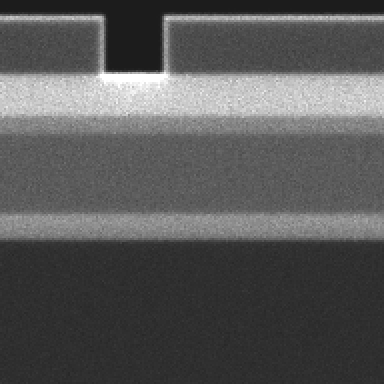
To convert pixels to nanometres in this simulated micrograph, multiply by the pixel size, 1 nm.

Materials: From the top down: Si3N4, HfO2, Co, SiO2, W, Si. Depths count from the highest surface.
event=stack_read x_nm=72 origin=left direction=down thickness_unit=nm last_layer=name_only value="Si3N4 58, HfO2 42, Co 18, SiO2 80, W 26, Si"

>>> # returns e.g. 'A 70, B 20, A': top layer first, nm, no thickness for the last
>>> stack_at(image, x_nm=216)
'Si3N4 58, HfO2 42, Co 18, SiO2 80, W 26, Si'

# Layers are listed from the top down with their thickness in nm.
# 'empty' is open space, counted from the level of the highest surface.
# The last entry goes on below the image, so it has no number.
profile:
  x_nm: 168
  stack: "Si3N4 58, HfO2 42, Co 18, SiO2 80, W 26, Si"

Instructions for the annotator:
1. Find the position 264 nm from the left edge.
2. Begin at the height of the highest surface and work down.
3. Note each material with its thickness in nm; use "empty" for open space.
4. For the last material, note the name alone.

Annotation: Si3N4 58, HfO2 42, Co 18, SiO2 80, W 26, Si